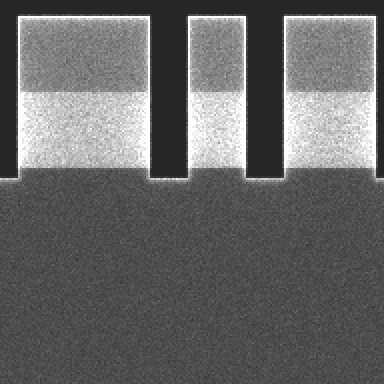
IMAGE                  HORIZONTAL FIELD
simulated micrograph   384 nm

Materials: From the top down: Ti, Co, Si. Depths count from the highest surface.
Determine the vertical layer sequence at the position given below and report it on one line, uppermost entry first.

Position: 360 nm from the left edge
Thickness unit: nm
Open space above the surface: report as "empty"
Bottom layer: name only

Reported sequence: Ti 76, Co 76, Si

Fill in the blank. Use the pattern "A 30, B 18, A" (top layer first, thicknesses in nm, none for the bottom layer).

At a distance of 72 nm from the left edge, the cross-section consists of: Ti 76, Co 76, Si